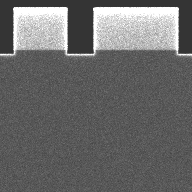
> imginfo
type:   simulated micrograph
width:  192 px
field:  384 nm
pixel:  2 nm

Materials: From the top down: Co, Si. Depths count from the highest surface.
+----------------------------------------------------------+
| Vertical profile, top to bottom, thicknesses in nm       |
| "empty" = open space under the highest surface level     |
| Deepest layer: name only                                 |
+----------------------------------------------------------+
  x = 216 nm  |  Co 84, Si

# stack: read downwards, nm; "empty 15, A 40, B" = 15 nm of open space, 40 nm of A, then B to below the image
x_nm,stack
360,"empty 92, Si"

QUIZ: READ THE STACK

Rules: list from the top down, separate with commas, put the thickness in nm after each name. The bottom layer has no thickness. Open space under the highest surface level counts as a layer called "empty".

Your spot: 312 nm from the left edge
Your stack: Co 84, Si